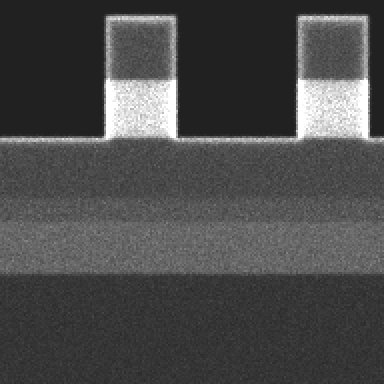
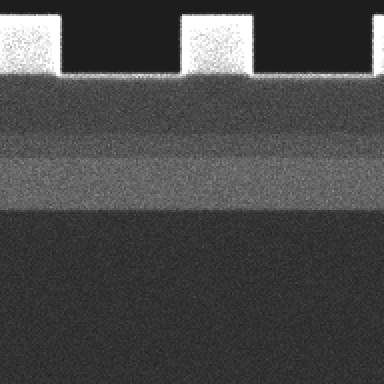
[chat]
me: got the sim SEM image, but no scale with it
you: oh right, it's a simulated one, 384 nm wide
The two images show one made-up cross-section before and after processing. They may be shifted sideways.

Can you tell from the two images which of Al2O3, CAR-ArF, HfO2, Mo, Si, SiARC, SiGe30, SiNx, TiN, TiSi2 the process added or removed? Yes, it removed SiARC.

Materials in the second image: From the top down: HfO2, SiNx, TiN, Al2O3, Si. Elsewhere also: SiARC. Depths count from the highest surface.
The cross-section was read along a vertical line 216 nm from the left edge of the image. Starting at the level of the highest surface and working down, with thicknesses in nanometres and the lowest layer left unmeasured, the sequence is HfO2 58, SiNx 60, TiN 24, Al2O3 52, Si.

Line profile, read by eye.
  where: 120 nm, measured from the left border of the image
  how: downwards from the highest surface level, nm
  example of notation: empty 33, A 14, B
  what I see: empty 58, SiNx 60, TiN 24, Al2O3 52, Si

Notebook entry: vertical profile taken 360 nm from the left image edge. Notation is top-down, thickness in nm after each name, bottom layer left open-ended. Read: empty 58, SiNx 60, TiN 24, Al2O3 52, Si